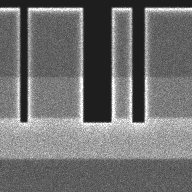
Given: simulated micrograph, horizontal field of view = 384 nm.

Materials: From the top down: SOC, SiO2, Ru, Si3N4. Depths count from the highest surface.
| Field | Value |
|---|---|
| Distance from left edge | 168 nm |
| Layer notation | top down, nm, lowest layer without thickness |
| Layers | empty 230, Ru 72, Si3N4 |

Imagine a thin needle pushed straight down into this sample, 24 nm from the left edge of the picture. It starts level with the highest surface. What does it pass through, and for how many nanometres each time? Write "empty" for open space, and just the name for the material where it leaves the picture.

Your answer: SOC 138, SiO2 82, Ru 82, Si3N4